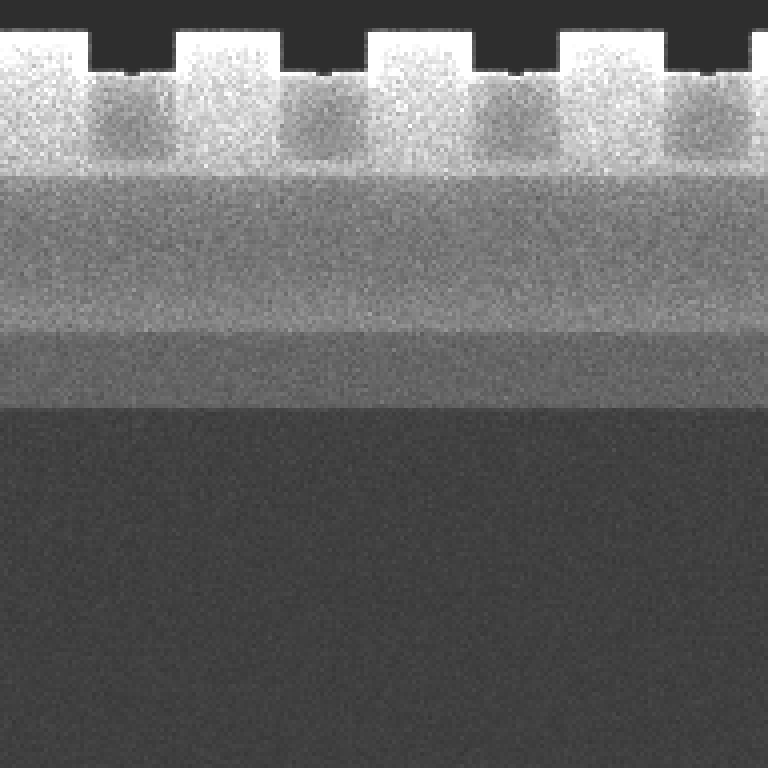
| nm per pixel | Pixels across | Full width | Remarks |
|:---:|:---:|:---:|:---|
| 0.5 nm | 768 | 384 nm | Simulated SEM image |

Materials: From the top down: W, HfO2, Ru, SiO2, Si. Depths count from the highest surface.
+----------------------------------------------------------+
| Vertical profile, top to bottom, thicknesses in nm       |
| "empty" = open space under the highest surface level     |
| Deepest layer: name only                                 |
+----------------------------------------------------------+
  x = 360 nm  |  empty 20, W 44, HfO2 8, Ru 78, SiO2 38, Si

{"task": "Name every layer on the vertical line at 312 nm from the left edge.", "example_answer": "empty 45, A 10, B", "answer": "HfO2 72, Ru 78, SiO2 38, Si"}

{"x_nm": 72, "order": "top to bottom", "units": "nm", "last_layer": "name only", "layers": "empty 20, W 44, HfO2 8, Ru 78, SiO2 38, Si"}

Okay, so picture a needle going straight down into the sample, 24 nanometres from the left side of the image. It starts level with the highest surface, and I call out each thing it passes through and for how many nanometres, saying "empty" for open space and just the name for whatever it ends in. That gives HfO2 72, Ru 78, SiO2 38, Si